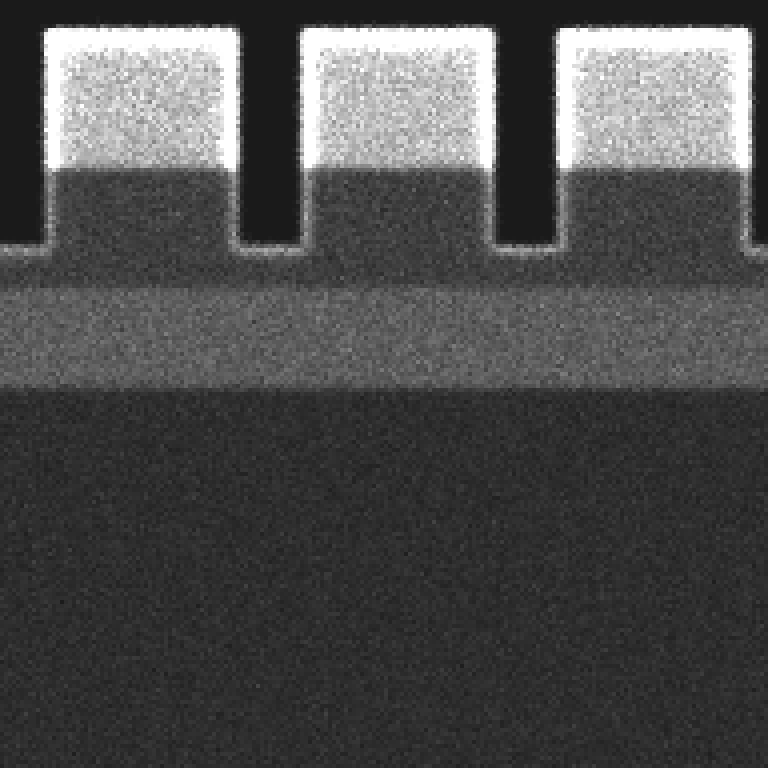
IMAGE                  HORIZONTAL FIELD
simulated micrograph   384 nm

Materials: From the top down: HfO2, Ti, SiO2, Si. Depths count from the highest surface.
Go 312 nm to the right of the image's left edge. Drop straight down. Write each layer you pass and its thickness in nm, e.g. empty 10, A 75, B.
HfO2 68, Ti 60, SiO2 50, Si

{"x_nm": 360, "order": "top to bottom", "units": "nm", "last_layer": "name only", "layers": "HfO2 68, Ti 60, SiO2 50, Si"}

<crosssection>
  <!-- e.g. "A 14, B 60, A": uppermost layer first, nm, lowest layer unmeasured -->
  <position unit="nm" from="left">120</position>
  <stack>empty 108, Ti 20, SiO2 50, Si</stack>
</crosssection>